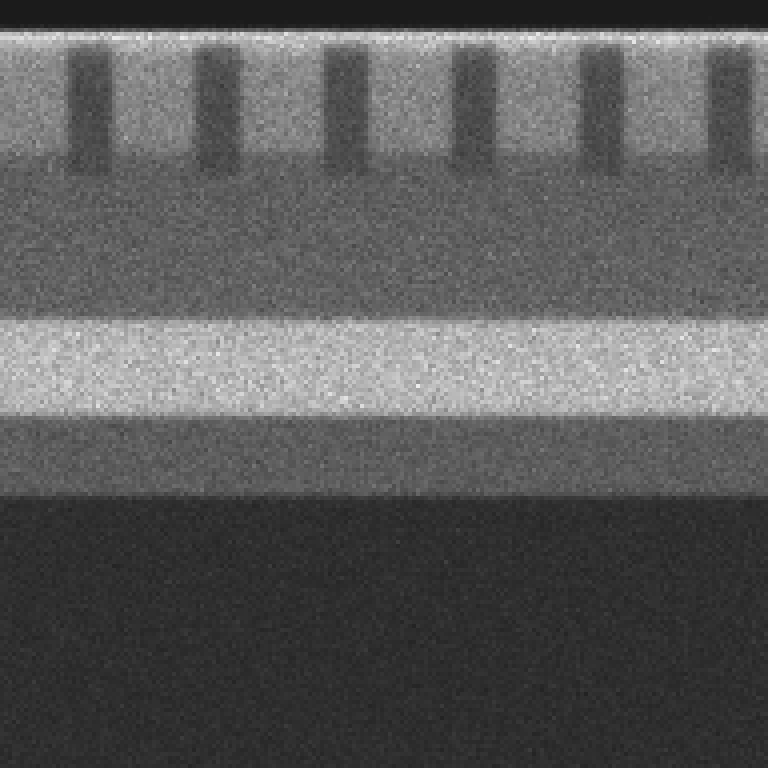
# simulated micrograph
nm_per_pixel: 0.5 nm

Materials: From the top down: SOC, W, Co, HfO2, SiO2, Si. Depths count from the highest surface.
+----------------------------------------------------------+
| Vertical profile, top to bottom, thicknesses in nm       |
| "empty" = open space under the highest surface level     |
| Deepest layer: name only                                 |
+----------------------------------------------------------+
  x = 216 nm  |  SOC 6, W 54, Co 84, HfO2 48, SiO2 40, Si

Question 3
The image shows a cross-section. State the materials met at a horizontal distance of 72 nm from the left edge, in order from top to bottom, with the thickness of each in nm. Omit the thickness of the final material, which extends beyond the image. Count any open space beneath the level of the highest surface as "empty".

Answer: SOC 6, W 54, Co 84, HfO2 48, SiO2 40, Si